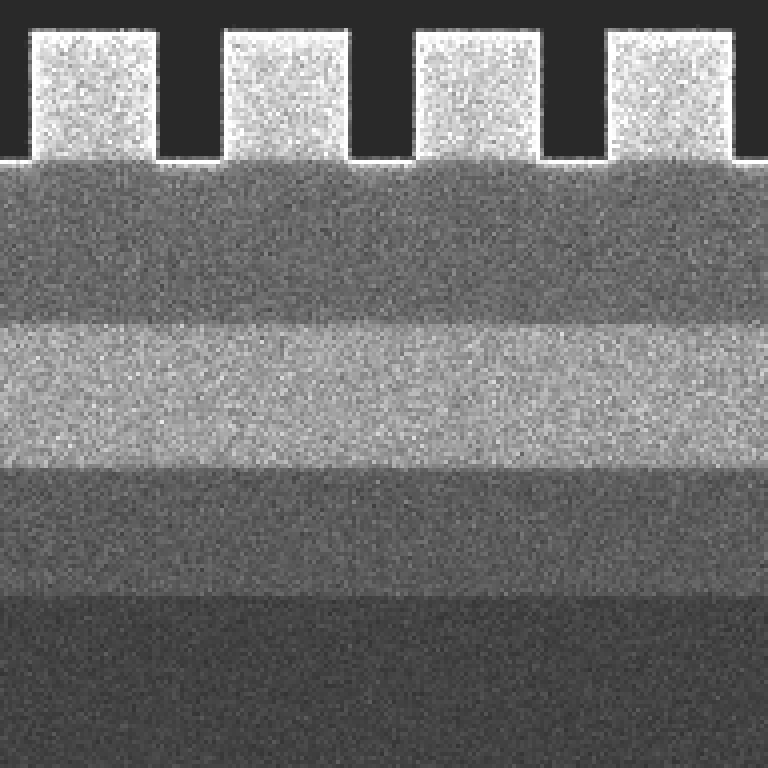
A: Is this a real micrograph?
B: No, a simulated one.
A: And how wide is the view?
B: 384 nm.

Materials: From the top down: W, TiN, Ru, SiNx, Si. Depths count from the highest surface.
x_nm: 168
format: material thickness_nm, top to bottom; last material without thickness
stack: W 64, TiN 82, Ru 72, SiNx 64, Si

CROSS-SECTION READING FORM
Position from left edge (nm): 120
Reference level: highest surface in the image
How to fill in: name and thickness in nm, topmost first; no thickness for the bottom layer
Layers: W 64, TiN 82, Ru 72, SiNx 64, Si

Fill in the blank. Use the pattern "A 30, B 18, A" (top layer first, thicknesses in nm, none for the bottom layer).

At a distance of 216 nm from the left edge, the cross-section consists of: W 64, TiN 82, Ru 72, SiNx 64, Si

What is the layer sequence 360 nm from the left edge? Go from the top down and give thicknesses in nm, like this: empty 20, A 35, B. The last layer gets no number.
W 64, TiN 82, Ru 72, SiNx 64, Si